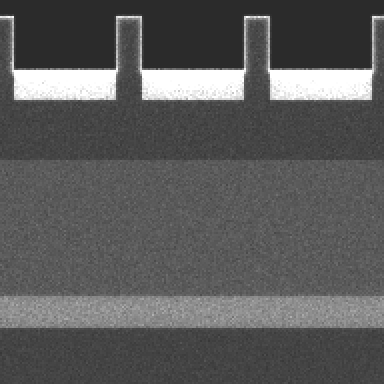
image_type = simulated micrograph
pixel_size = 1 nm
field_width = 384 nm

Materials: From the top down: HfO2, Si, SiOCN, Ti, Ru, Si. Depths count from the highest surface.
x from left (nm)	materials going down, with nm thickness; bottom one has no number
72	empty 54, HfO2 30, Si 60, SiOCN 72, Ti 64, Ru 32, Si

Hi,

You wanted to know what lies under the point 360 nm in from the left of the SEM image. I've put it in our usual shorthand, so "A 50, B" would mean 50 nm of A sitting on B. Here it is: empty 54, HfO2 30, Si 60, SiOCN 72, Ti 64, Ru 32, Si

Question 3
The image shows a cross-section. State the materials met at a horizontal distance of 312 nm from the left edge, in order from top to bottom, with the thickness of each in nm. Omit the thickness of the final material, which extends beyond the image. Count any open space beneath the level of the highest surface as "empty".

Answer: empty 54, HfO2 30, Si 60, SiOCN 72, Ti 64, Ru 32, Si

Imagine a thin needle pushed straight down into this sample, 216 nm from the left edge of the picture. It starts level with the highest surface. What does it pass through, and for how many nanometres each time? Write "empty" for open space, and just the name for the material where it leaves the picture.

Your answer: empty 54, HfO2 30, Si 60, SiOCN 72, Ti 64, Ru 32, Si